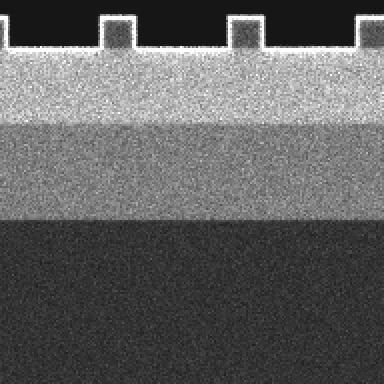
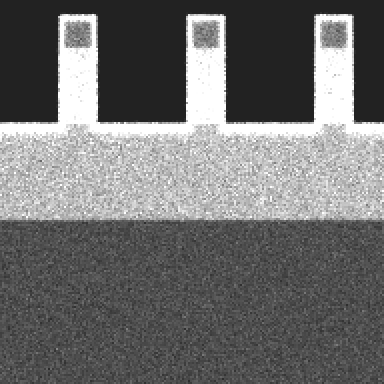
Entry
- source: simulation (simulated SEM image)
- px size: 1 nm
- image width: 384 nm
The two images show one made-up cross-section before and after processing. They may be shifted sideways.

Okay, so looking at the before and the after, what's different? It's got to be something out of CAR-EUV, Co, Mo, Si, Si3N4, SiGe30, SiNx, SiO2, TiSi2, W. W, removed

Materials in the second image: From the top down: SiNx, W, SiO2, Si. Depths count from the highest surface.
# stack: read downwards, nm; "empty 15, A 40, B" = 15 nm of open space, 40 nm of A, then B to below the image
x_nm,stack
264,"empty 108, SiO2 96, Si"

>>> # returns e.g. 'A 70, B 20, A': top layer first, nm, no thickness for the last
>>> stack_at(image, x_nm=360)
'empty 108, SiO2 96, Si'